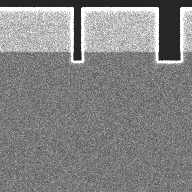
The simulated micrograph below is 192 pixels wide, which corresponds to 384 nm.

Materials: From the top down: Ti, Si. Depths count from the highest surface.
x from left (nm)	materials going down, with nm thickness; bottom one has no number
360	empty 106, Si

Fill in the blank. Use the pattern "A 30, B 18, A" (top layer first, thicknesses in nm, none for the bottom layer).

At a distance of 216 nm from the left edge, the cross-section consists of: Ti 88, Si